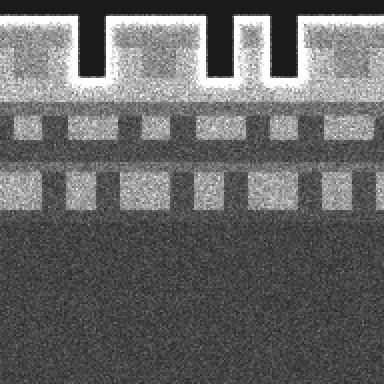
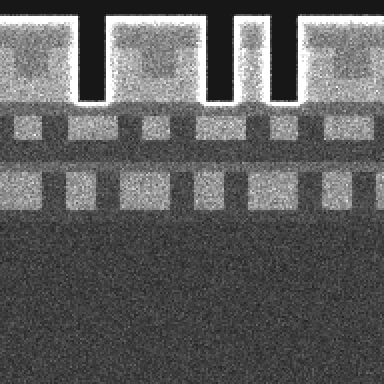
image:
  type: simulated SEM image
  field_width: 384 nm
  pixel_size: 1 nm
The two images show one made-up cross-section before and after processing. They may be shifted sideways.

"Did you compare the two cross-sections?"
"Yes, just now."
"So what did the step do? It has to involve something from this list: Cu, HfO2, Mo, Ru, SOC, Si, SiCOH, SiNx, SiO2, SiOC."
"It removed SiO2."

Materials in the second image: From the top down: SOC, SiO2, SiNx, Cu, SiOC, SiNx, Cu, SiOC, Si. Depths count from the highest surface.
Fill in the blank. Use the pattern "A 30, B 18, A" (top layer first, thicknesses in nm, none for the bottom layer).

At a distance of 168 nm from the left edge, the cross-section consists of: SOC 62, SiO2 24, SiNx 14, Cu 24, SiOC 22, SiNx 10, Cu 38, SiOC 12, Si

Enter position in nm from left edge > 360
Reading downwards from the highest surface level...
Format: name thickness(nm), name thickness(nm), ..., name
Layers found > SOC 62, SiO2 24, SiNx 14, Cu 24, SiOC 22, SiNx 10, SiOC 50, Si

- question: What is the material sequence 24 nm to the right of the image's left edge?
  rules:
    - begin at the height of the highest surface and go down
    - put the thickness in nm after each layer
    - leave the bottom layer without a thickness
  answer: SOC 62, SiO2 24, SiNx 14, Cu 24, SiOC 22, SiNx 10, Cu 38, SiOC 12, Si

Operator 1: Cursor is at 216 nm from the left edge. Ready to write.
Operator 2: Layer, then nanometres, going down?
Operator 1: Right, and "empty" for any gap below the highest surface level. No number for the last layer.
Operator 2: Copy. empty 86, SiNx 14, Cu 24, SiOC 22, SiNx 10, Cu 38, SiOC 12, Si